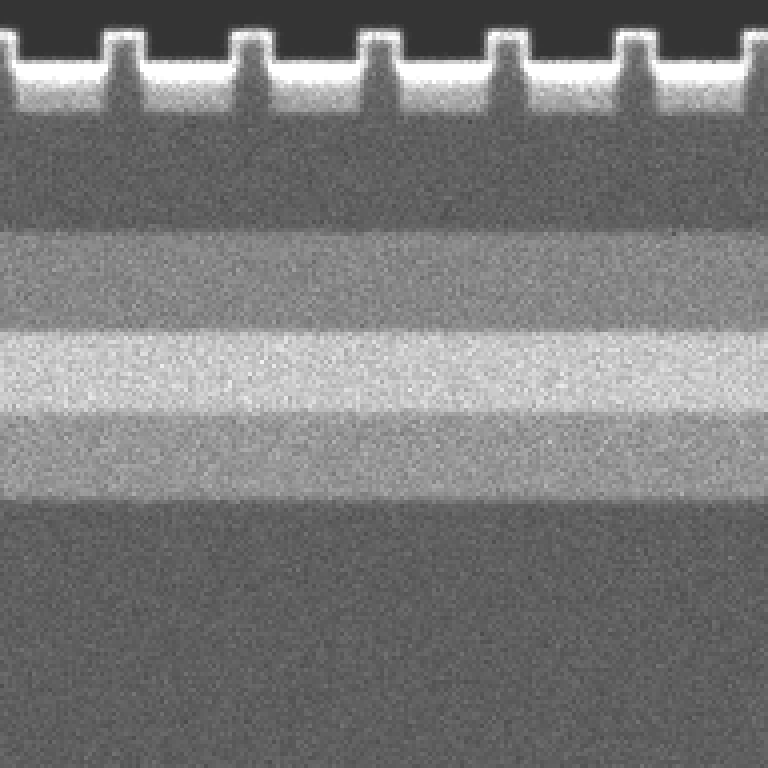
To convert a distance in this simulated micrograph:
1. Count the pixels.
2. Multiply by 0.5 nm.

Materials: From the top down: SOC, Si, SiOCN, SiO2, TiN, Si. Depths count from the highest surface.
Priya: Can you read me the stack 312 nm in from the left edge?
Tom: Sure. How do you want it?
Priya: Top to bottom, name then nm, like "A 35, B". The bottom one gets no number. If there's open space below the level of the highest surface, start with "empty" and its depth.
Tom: Si 100, SiOCN 50, SiO2 40, TiN 44, Si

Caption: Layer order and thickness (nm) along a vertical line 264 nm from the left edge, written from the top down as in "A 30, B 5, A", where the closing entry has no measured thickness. empty 16, SOC 24, Si 60, SiOCN 50, SiO2 40, TiN 44, Si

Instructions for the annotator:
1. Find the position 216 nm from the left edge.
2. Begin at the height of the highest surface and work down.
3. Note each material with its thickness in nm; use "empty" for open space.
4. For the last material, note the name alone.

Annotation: empty 16, SOC 24, Si 60, SiOCN 50, SiO2 40, TiN 44, Si